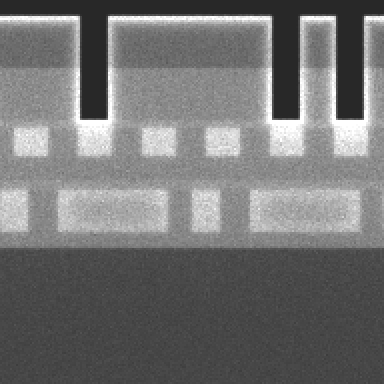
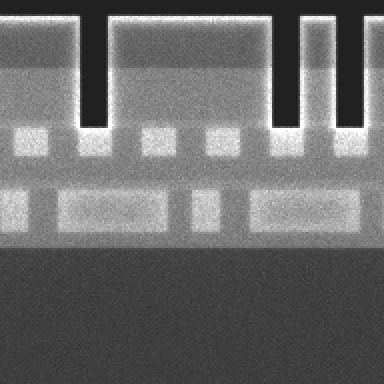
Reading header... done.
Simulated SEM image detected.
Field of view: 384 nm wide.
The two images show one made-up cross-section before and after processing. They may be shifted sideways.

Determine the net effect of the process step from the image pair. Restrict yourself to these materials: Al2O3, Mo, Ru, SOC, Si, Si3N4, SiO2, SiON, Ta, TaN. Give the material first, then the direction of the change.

Al2O3: removed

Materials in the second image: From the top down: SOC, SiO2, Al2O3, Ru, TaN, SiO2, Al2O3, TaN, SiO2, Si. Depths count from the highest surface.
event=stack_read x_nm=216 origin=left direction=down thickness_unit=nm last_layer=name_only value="SOC 52, SiO2 52, Al2O3 8, Ru 18, TaN 10, SiO2 24, Al2O3 10, TaN 42, SiO2 16, Si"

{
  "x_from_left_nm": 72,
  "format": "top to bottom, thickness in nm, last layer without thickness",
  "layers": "SOC 52, SiO2 52, Al2O3 8, SiO2 52, Al2O3 10, Ru 32, TaN 10, SiO2 16, Si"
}